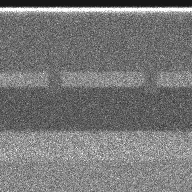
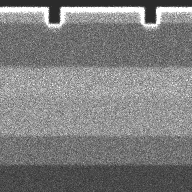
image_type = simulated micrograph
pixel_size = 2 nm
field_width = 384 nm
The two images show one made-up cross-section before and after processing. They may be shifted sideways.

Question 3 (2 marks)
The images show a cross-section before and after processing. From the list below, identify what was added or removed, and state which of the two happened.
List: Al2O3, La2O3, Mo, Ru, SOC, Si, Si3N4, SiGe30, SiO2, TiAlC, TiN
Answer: SOC was removed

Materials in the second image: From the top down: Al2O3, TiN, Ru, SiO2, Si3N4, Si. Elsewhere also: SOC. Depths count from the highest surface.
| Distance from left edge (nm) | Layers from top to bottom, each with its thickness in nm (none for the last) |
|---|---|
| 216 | Al2O3 30, TiN 88, Ru 60, SiO2 78, Si3N4 58, Si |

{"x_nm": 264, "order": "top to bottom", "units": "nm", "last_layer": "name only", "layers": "Al2O3 30, TiN 88, Ru 60, SiO2 78, Si3N4 58, Si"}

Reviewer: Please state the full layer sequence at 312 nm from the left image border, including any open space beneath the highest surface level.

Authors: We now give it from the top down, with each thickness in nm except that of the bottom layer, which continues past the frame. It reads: empty 32, SOC 10, TiN 76, Ru 60, SiO2 78, Si3N4 58, Si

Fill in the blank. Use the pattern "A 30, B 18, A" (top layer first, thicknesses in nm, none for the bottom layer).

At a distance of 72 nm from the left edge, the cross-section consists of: Al2O3 30, TiN 88, Ru 60, SiO2 78, Si3N4 58, Si